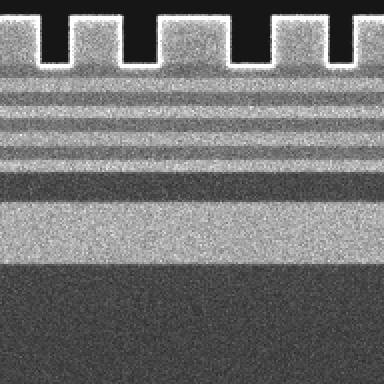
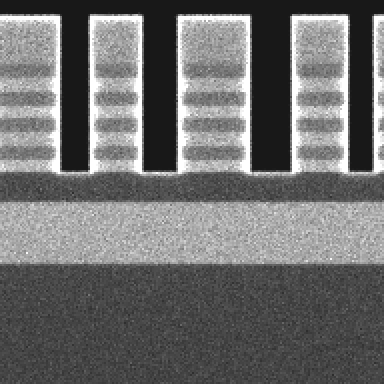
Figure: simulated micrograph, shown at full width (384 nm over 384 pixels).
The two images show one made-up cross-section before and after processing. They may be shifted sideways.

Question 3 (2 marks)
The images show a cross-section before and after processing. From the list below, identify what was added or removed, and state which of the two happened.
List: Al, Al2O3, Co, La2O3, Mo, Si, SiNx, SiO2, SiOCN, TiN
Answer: Al2O3 and SiNx and SiO2 was removed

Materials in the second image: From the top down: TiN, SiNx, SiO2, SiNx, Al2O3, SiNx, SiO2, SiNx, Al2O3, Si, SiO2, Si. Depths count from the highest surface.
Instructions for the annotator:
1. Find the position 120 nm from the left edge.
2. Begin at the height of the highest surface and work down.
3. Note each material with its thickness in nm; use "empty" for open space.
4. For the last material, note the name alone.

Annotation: TiN 48, SiNx 14, SiO2 14, SiNx 14, Al2O3 12, SiNx 14, SiO2 14, SiNx 14, Al2O3 12, Si 30, SiO2 62, Si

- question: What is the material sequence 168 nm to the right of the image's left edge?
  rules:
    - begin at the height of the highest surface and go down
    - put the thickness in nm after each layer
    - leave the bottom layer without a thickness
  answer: empty 156, Si 30, SiO2 62, Si